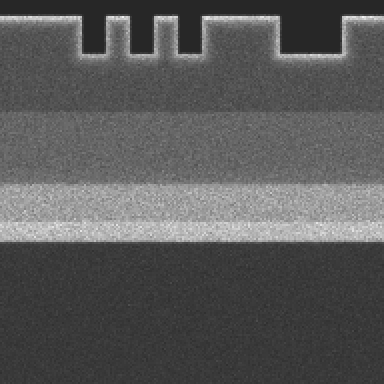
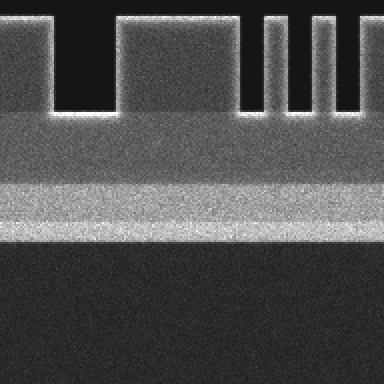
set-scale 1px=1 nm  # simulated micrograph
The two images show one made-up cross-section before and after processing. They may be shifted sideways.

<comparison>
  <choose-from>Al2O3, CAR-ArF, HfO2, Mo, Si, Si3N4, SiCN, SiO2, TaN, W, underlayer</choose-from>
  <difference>underlayer removed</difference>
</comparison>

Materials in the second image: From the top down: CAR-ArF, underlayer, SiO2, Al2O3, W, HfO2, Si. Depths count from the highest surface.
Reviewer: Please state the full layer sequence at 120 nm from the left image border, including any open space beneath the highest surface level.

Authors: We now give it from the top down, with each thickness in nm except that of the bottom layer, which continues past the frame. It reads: CAR-ArF 38, underlayer 58, SiO2 58, Al2O3 14, W 38, HfO2 20, Si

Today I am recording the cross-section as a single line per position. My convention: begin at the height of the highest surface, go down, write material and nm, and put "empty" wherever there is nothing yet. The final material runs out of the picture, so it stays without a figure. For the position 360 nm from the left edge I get CAR-ArF 38, underlayer 58, SiO2 58, Al2O3 14, W 38, HfO2 20, Si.